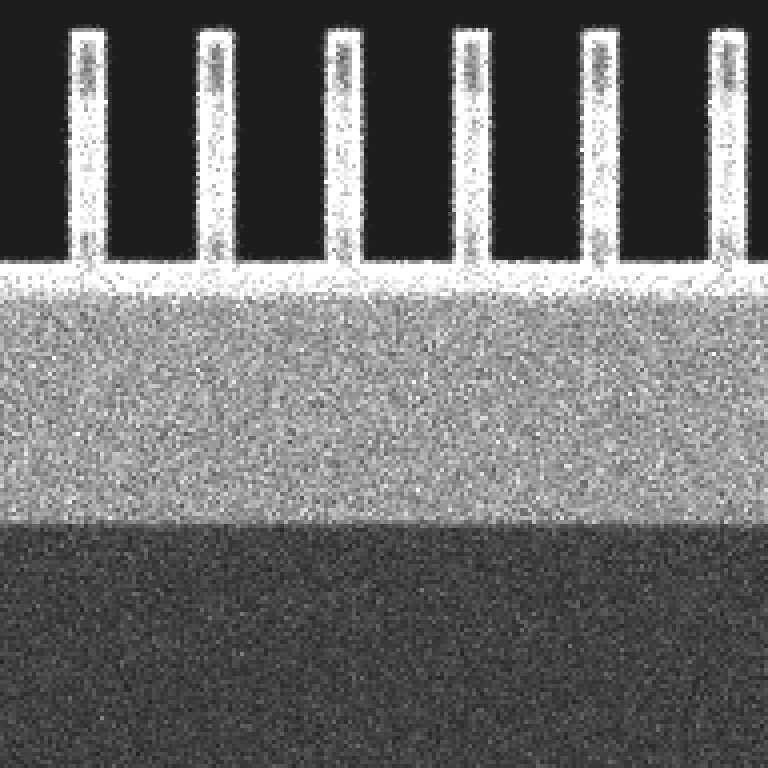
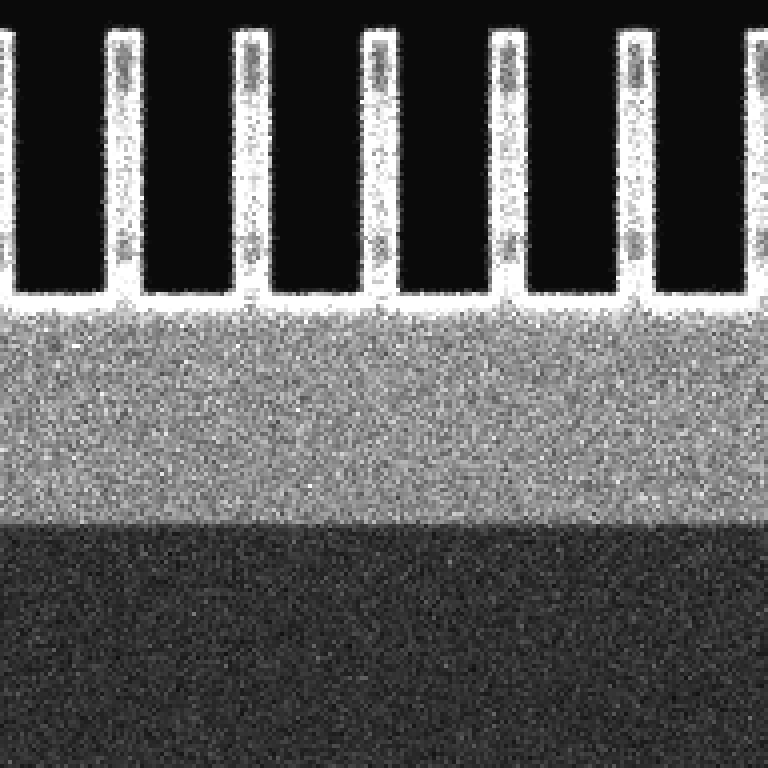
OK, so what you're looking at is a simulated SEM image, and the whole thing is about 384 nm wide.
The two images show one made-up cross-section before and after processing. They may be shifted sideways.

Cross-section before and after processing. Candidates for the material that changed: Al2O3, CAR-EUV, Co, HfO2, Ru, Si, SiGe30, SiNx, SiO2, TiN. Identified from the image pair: Ru (removed).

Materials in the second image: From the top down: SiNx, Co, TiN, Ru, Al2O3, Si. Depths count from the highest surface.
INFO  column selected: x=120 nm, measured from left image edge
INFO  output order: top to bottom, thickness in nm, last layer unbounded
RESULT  SiNx 30, Co 70, TiN 16, Ru 16, Al2O3 114, Si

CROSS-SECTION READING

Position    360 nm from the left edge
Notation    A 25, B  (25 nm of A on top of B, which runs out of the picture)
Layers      empty 132, Al2O3 114, Si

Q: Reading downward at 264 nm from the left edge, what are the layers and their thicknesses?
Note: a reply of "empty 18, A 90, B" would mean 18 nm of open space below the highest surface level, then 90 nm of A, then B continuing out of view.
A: empty 132, Al2O3 114, Si